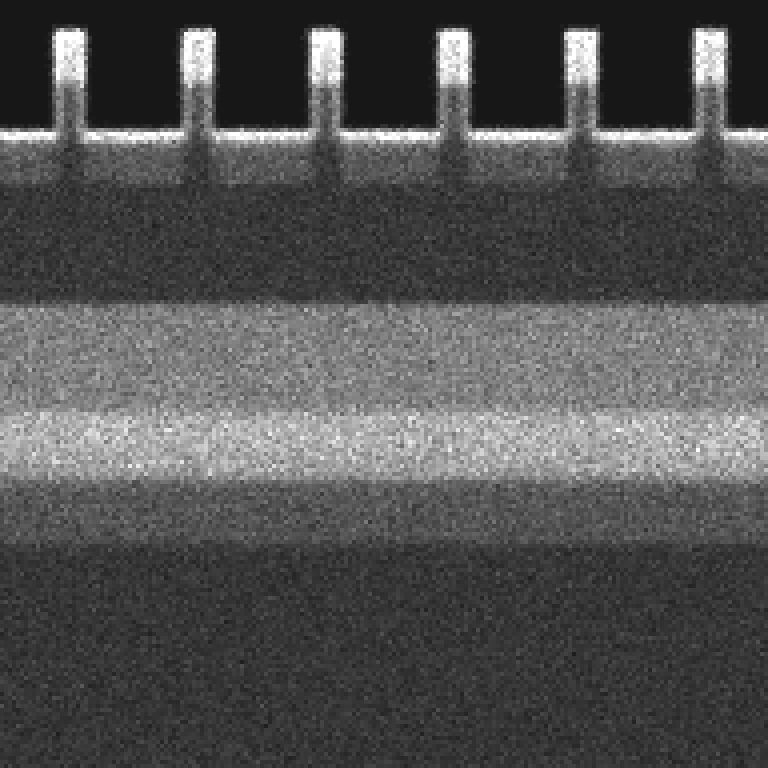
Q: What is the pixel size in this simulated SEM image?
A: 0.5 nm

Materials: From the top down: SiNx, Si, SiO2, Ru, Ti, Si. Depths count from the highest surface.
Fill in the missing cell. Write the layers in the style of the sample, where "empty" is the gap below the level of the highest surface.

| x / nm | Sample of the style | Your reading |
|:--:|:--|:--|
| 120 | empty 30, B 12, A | empty 50, SiNx 26, Si 60, SiO2 54, Ru 34, Ti 32, Si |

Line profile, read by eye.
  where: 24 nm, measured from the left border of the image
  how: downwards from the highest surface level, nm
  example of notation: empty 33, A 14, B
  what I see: empty 50, SiNx 26, Si 60, SiO2 54, Ru 34, Ti 32, Si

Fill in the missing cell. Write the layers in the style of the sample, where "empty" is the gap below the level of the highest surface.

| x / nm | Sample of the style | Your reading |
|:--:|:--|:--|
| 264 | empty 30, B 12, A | empty 50, SiNx 26, Si 60, SiO2 54, Ru 34, Ti 32, Si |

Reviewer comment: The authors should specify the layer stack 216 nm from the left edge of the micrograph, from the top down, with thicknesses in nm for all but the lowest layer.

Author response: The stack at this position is empty 50, SiNx 26, Si 60, SiO2 54, Ru 34, Ti 32, Si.